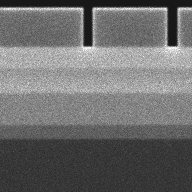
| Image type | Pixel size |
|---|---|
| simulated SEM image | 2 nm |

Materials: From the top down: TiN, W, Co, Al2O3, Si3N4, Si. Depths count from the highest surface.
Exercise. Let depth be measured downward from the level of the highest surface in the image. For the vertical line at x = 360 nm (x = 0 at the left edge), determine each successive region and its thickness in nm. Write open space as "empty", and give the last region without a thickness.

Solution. TiN 78, W 42, Co 50, Al2O3 64, Si3N4 28, Si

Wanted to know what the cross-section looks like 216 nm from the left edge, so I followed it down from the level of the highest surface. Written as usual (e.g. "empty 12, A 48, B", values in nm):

TiN 78, W 42, Co 50, Al2O3 64, Si3N4 28, Si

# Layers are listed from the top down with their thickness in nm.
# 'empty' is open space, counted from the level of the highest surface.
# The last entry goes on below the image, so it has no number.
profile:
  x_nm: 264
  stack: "TiN 78, W 42, Co 50, Al2O3 64, Si3N4 28, Si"